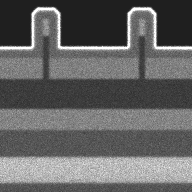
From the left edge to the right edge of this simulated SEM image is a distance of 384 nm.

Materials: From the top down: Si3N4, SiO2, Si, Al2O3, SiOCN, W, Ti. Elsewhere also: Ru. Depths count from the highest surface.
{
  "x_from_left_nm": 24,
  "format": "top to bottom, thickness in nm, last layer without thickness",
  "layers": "empty 78, Si3N4 22, SiO2 42, Si 60, Al2O3 42, SiOCN 54, W 52, Ti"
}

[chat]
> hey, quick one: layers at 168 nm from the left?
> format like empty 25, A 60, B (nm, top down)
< empty 78, Si3N4 22, SiO2 42, Si 60, Al2O3 42, SiOCN 54, W 52, Ti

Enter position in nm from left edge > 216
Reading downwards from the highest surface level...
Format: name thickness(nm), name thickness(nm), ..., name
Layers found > empty 78, Si3N4 22, SiO2 42, Si 60, Al2O3 42, SiOCN 54, W 52, Ti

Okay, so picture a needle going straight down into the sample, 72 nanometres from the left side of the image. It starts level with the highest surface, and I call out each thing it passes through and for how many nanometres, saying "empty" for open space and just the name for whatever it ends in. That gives empty 2, Si3N4 98, SiO2 42, Si 60, Al2O3 42, SiOCN 54, W 52, Ti